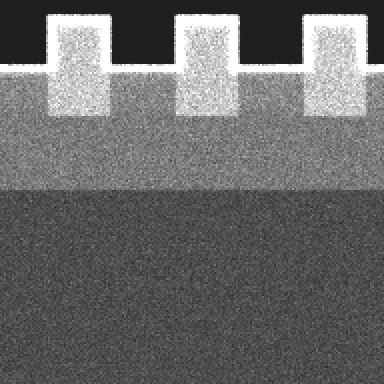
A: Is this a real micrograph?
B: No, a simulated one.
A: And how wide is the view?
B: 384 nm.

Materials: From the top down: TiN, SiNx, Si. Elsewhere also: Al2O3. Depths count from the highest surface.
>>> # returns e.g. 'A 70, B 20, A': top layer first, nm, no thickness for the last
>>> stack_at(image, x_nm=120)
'empty 50, TiN 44, SiNx 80, Si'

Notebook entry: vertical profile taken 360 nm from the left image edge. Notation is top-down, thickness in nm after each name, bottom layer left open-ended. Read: Al2O3 100, SiNx 74, Si